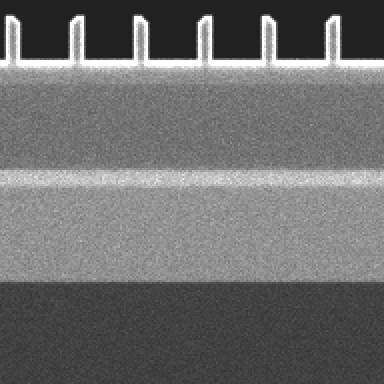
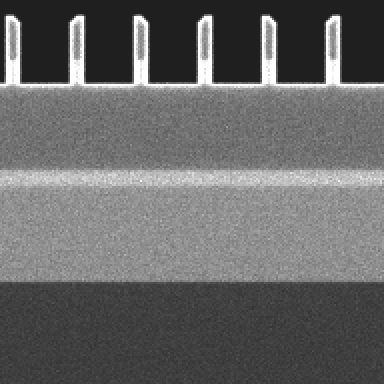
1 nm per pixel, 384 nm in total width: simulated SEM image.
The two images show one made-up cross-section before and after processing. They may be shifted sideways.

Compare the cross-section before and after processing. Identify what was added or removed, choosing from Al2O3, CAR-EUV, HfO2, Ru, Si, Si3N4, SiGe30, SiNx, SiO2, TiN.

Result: SiO2 removed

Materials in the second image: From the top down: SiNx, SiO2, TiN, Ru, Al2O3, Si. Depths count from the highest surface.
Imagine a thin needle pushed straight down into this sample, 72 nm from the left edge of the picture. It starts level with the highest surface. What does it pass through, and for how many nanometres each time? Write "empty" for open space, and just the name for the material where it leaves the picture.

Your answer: empty 4, SiNx 40, SiO2 24, TiN 86, Ru 16, Al2O3 96, Si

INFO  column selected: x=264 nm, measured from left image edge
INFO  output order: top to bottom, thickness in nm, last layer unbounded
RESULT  SiNx 44, SiO2 24, TiN 86, Ru 16, Al2O3 96, Si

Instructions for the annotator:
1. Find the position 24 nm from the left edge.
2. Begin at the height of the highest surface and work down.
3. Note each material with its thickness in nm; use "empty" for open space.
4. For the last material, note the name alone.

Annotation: empty 68, TiN 86, Ru 16, Al2O3 96, Si